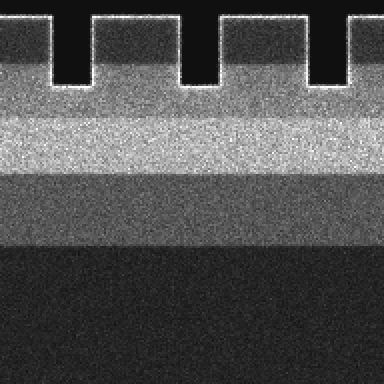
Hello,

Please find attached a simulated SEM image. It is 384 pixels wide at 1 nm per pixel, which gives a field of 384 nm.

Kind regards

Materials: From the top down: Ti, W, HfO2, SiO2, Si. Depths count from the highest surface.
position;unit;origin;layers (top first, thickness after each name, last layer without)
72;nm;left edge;empty 70, W 32, HfO2 56, SiO2 72, Si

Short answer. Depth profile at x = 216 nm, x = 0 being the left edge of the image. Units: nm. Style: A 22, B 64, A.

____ empty 70, W 32, HfO2 56, SiO2 72, Si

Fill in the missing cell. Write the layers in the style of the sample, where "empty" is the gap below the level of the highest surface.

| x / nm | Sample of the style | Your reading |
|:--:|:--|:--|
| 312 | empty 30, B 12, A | empty 70, W 32, HfO2 56, SiO2 72, Si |